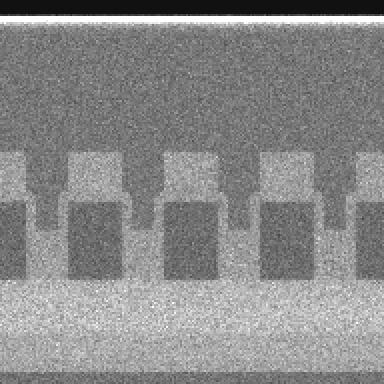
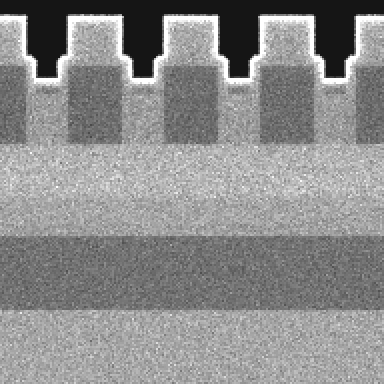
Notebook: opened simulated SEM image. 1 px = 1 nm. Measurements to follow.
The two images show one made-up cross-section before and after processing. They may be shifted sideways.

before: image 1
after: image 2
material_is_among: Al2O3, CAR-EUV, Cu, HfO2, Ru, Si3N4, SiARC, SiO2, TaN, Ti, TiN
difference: SiARC, removed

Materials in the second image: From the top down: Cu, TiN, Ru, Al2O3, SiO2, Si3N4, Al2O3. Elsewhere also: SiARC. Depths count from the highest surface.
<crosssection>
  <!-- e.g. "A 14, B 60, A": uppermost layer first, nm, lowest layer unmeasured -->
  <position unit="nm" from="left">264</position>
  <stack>Cu 50, TiN 78, Ru 54, Al2O3 26, SiO2 12, Si3N4 74, Al2O3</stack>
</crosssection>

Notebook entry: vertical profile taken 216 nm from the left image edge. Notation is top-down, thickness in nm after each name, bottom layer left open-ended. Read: Cu 50, TiN 78, Ru 54, Al2O3 26, SiO2 12, Si3N4 74, Al2O3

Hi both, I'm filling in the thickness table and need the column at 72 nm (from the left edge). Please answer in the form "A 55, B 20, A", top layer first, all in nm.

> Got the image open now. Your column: Cu 50, TiN 78, Ru 54, Al2O3 26, SiO2 12, Si3N4 74, Al2O3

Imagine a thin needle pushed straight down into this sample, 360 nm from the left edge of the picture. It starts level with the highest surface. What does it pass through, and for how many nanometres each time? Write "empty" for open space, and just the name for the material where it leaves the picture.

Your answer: Cu 50, TiN 78, Ru 54, Al2O3 26, SiO2 12, Si3N4 74, Al2O3